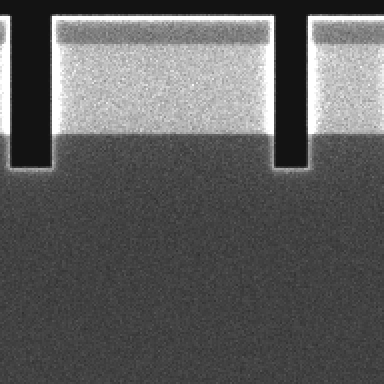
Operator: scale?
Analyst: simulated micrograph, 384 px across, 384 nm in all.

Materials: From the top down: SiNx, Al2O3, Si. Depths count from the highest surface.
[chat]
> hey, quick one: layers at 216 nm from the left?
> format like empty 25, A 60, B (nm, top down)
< SiNx 28, Al2O3 90, Si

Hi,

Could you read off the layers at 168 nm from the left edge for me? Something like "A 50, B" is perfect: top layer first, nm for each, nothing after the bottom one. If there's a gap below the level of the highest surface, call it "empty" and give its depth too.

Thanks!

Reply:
SiNx 28, Al2O3 90, Si